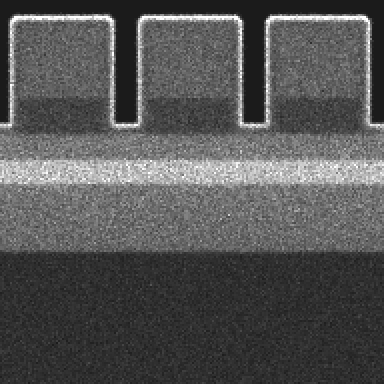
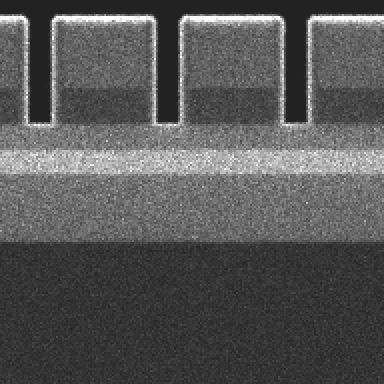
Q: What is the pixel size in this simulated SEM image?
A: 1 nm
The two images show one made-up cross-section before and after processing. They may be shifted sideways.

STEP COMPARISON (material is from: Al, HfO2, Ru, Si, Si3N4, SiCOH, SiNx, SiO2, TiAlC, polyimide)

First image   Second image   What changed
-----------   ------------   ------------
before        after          Si3N4, removed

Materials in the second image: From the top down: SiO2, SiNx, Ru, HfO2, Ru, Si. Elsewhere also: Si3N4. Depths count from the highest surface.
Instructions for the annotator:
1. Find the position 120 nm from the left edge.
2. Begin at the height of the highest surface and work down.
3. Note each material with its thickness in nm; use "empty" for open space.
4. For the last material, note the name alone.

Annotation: SiO2 72, SiNx 36, Ru 26, HfO2 24, Ru 68, Si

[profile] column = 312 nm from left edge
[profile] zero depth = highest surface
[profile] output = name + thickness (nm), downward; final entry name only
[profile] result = Si3N4 108, Ru 26, HfO2 24, Ru 68, Si